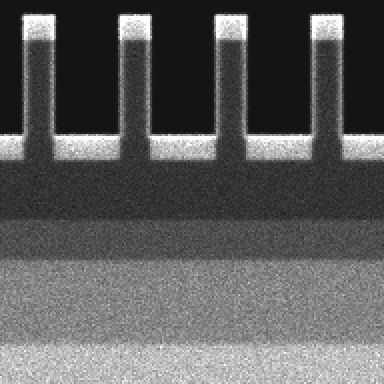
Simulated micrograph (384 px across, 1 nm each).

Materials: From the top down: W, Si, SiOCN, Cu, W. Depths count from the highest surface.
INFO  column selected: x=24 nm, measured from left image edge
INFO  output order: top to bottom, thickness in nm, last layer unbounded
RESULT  W 24, Si 180, SiOCN 40, Cu 84, W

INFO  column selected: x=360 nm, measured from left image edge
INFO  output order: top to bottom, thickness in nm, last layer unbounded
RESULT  empty 120, W 24, Si 60, SiOCN 40, Cu 84, W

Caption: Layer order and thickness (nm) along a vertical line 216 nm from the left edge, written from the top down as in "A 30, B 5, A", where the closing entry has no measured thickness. W 24, Si 180, SiOCN 40, Cu 84, W